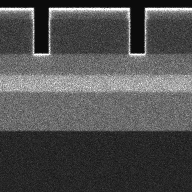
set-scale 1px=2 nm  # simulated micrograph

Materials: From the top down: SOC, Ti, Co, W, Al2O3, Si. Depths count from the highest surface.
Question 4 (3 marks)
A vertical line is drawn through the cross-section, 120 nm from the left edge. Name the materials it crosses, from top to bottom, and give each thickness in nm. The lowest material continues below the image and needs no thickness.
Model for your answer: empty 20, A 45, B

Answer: SOC 22, Ti 70, Co 42, W 34, Al2O3 78, Si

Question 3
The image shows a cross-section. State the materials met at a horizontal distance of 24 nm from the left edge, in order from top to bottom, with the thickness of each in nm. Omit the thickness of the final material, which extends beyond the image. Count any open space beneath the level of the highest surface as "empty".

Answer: SOC 22, Ti 70, Co 42, W 34, Al2O3 78, Si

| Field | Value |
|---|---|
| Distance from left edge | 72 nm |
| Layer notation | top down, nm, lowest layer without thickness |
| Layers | empty 92, Co 42, W 34, Al2O3 78, Si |